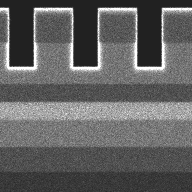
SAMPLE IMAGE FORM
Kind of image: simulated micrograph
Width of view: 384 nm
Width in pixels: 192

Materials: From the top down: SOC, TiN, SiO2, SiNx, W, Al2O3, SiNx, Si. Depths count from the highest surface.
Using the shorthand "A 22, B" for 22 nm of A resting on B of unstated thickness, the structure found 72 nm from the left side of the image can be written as SOC 12, TiN 58, SiO2 82, SiNx 36, W 36, Al2O3 54, SiNx 50, Si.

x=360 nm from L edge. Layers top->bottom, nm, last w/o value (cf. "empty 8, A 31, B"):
SOC 12, TiN 58, SiO2 82, SiNx 36, W 36, Al2O3 54, SiNx 50, Si